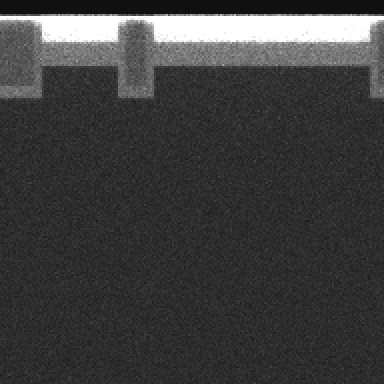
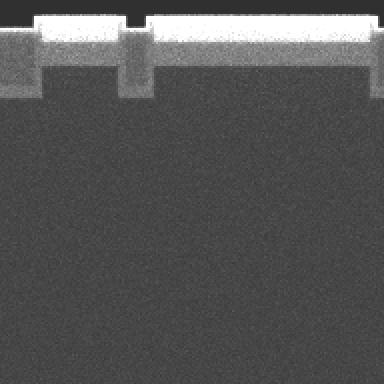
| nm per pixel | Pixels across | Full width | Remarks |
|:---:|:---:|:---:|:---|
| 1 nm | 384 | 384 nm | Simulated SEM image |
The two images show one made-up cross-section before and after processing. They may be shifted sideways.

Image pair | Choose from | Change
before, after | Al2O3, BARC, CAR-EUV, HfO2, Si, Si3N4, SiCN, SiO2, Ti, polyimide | Si3N4 (removed)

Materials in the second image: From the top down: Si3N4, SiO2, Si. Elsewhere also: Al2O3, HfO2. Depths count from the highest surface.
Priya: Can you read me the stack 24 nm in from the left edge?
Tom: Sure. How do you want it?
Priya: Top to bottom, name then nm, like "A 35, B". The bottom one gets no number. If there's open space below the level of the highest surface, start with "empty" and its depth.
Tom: empty 12, Si3N4 58, SiO2 12, Si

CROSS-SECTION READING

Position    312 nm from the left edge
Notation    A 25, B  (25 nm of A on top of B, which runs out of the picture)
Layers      HfO2 26, Al2O3 24, Si